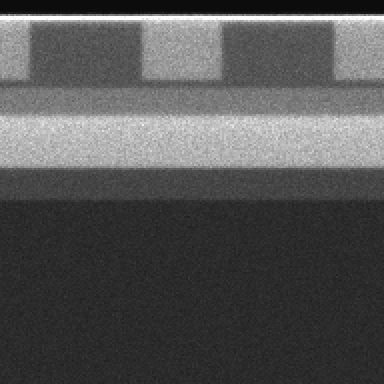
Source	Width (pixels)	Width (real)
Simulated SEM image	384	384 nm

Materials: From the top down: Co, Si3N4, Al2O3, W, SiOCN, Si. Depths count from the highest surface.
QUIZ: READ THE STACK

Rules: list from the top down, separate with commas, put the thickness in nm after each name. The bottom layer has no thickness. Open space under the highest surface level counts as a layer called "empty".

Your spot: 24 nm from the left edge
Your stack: Co 64, Si3N4 8, Al2O3 28, W 52, SiOCN 32, Si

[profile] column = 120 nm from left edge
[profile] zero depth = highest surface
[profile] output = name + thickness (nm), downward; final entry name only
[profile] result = Si3N4 72, Al2O3 28, W 52, SiOCN 32, Si